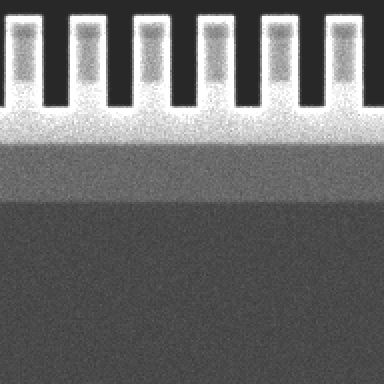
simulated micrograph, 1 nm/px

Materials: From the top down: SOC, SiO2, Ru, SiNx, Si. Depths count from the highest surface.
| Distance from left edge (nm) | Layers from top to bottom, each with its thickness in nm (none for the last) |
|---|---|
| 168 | SOC 22, SiO2 44, Ru 62, SiNx 58, Si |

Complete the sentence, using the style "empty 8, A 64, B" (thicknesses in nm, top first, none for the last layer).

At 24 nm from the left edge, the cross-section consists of SOC 22, SiO2 44, Ru 62, SiNx 58, Si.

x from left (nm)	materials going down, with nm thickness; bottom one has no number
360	SOC 22, SiO2 44, Ru 62, SiNx 58, Si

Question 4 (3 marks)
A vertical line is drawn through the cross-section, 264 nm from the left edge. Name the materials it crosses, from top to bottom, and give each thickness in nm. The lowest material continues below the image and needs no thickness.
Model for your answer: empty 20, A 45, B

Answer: SOC 22, SiO2 44, Ru 62, SiNx 58, Si